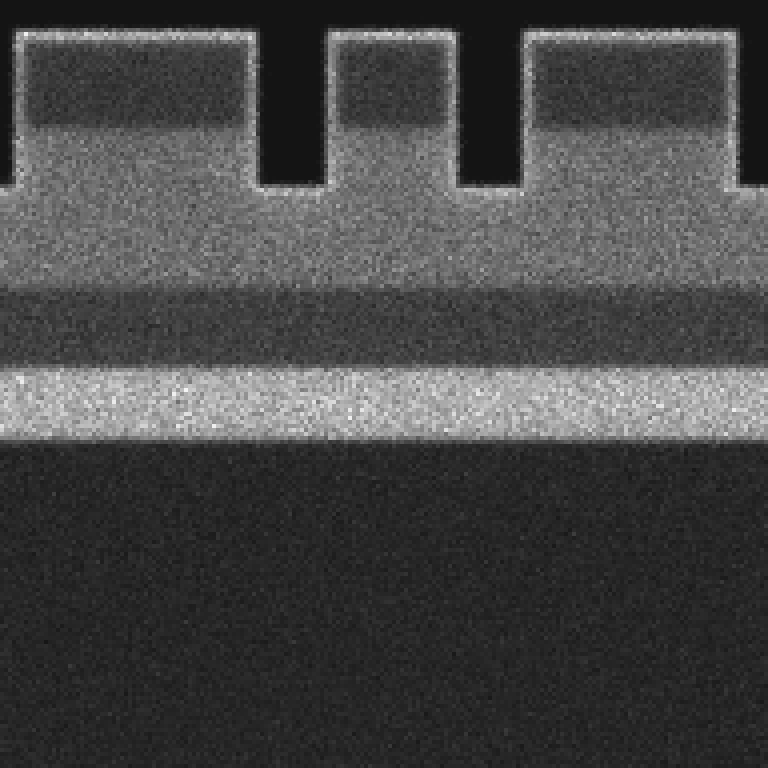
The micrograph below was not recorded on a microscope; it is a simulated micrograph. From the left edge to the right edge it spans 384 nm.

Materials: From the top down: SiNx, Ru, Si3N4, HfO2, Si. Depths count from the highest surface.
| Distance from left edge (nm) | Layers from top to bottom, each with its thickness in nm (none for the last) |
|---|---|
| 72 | SiNx 48, Ru 80, Si3N4 40, HfO2 36, Si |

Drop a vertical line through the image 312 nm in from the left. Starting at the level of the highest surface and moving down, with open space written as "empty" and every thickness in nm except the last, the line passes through SiNx 48, Ru 80, Si3N4 40, HfO2 36, Si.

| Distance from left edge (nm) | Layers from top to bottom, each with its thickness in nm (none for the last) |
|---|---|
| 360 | SiNx 48, Ru 80, Si3N4 40, HfO2 36, Si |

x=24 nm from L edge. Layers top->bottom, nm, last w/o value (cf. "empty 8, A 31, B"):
SiNx 48, Ru 80, Si3N4 40, HfO2 36, Si